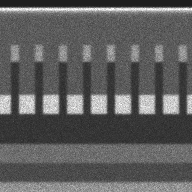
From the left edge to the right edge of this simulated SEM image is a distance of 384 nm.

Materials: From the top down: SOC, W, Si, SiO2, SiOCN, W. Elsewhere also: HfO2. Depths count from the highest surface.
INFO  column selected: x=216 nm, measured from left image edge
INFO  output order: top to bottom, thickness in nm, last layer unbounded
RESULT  SOC 74, W 34, Si 164, SiO2 38, SiOCN 38, W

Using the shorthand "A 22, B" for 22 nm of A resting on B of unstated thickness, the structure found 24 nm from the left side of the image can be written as SOC 74, W 34, Si 164, SiO2 38, SiOCN 38, W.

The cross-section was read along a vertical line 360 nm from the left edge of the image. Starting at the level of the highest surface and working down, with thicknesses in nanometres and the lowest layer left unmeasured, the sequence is SOC 74, W 34, Si 164, SiO2 38, SiOCN 38, W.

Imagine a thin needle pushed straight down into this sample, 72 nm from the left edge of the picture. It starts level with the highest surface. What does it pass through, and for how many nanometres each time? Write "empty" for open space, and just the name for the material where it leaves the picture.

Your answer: SOC 74, W 34, Si 164, SiO2 38, SiOCN 38, W